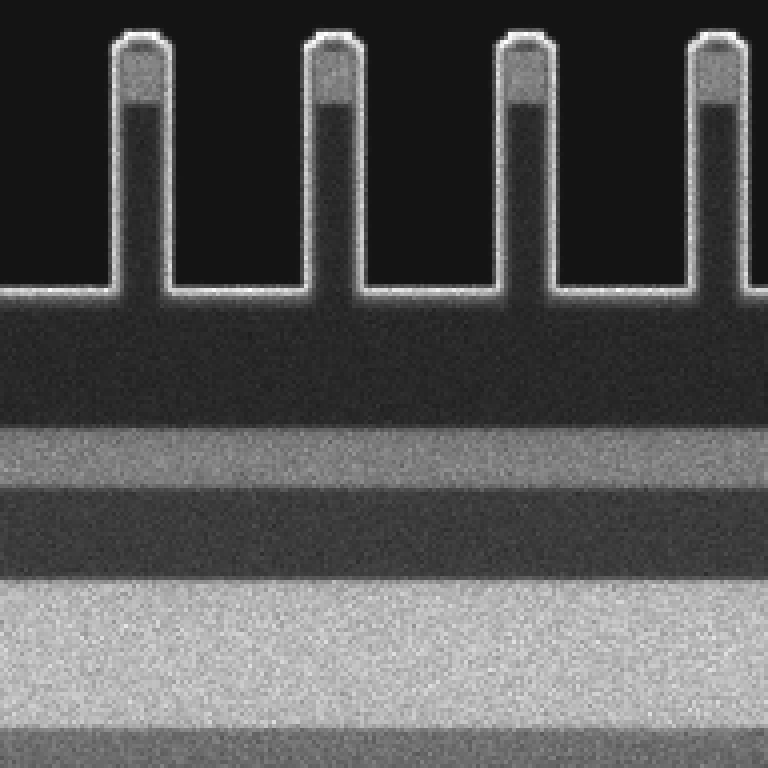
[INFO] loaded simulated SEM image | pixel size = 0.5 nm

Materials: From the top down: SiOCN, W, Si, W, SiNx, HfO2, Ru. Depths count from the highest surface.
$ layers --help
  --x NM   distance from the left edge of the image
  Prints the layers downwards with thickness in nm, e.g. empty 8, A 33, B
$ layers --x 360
SiOCN 10, W 26, Si 162, W 30, SiNx 46, HfO2 74, Ru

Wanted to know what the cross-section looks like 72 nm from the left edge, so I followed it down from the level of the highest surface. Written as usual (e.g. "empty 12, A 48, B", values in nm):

SiOCN 10, W 26, Si 162, W 30, SiNx 46, HfO2 74, Ru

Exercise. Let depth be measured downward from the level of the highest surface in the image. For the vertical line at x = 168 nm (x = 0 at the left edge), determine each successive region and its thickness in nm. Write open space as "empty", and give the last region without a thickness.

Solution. SiOCN 10, W 26, Si 162, W 30, SiNx 46, HfO2 74, Ru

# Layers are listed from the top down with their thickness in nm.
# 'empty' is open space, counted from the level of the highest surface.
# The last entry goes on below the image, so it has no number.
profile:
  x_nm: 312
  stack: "empty 128, SiOCN 10, Si 60, W 30, SiNx 46, HfO2 74, Ru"